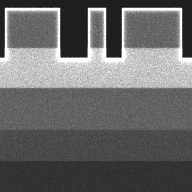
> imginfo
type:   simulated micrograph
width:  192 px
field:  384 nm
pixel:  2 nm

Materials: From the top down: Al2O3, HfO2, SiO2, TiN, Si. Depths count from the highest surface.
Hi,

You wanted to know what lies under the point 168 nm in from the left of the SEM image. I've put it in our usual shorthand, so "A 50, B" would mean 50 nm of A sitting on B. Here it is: empty 100, HfO2 60, SiO2 84, TiN 62, Si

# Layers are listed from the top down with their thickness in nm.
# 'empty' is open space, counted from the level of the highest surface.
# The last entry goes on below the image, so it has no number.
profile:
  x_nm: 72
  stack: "Al2O3 80, HfO2 80, SiO2 84, TiN 62, Si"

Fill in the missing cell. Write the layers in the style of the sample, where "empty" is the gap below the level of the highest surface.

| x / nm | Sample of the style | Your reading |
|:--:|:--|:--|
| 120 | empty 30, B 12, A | empty 100, HfO2 60, SiO2 84, TiN 62, Si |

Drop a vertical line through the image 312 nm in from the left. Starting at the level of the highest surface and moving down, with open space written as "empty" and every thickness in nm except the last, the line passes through Al2O3 80, HfO2 80, SiO2 84, TiN 62, Si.